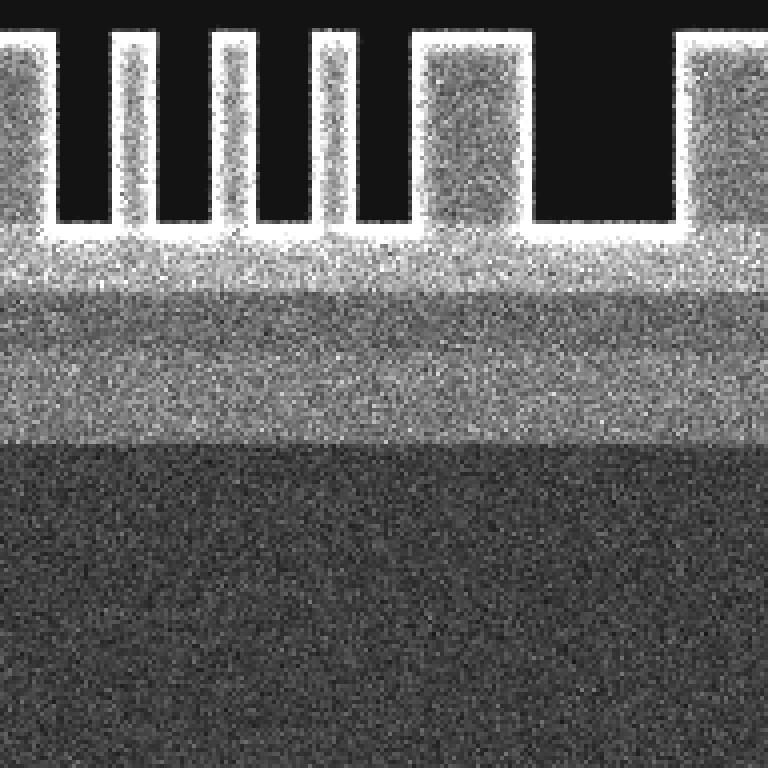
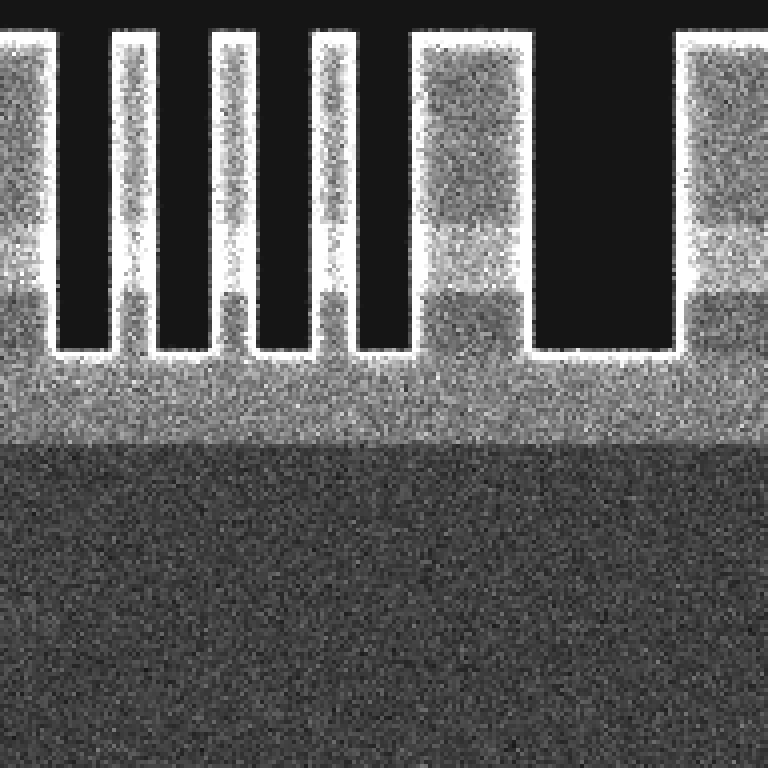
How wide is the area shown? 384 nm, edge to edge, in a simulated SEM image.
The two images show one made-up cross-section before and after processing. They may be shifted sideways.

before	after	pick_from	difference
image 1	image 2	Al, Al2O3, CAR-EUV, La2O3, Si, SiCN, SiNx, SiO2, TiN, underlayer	SiNx and SiO2 removed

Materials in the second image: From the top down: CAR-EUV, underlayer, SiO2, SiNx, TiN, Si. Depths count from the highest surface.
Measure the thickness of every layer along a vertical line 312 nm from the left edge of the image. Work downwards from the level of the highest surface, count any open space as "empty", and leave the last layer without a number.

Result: empty 160, TiN 46, Si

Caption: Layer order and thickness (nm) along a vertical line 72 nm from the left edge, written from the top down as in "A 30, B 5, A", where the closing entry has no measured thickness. CAR-EUV 36, underlayer 60, SiO2 34, SiNx 30, TiN 46, Si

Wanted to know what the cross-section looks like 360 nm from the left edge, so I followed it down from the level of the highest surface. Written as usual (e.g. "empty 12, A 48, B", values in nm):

CAR-EUV 36, underlayer 60, SiO2 34, SiNx 30, TiN 46, Si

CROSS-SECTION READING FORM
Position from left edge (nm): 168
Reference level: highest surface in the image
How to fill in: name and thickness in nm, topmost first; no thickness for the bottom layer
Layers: CAR-EUV 36, underlayer 60, SiO2 34, SiNx 30, TiN 46, Si